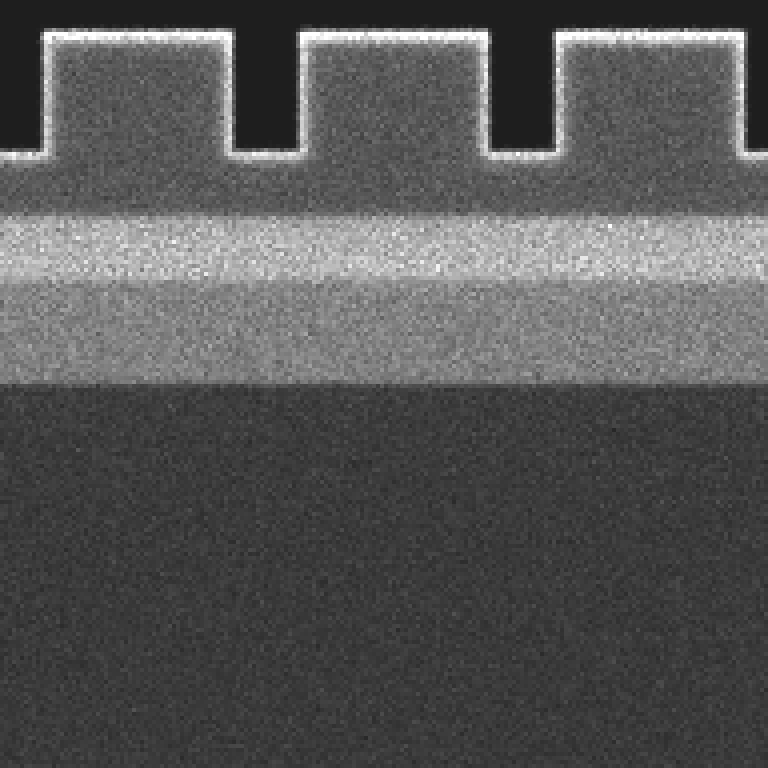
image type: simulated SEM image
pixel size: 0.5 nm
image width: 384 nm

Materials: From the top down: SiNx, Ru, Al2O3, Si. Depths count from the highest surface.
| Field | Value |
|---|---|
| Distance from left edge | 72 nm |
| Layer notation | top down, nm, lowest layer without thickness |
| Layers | SiNx 92, Ru 32, Al2O3 52, Si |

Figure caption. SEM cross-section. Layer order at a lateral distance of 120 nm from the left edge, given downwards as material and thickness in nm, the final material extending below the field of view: empty 60, SiNx 32, Ru 32, Al2O3 52, Si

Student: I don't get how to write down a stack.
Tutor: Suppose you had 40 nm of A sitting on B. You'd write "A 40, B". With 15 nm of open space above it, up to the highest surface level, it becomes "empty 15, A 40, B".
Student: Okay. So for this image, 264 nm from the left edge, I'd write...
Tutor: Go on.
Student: empty 60, SiNx 32, Ru 32, Al2O3 52, Si